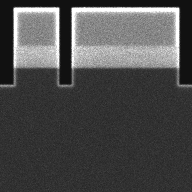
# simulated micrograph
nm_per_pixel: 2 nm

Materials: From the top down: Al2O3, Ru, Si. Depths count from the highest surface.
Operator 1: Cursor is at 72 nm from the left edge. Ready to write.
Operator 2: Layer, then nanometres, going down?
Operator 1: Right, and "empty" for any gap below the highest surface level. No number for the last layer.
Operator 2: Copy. Al2O3 76, Ru 44, Si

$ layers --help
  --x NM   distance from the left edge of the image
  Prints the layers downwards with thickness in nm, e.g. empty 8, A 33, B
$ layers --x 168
Al2O3 76, Ru 44, Si